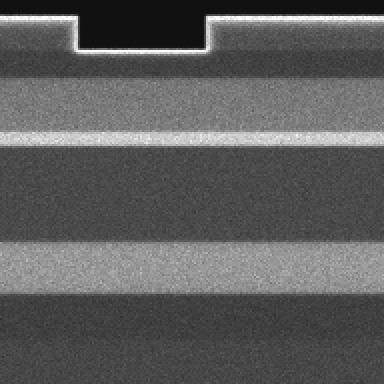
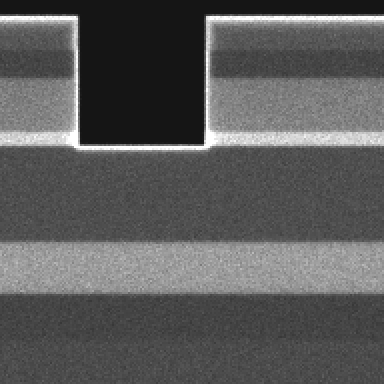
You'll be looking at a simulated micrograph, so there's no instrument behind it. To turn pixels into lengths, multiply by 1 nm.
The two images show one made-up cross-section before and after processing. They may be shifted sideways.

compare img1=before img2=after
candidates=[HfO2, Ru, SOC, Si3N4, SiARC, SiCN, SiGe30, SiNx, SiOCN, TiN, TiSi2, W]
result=removed:HfO2 and Ru and SiNx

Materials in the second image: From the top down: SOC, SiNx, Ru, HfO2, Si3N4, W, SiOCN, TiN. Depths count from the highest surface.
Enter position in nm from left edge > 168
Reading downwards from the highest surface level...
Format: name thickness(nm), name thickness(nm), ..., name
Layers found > empty 130, Si3N4 96, W 52, SiOCN 46, TiN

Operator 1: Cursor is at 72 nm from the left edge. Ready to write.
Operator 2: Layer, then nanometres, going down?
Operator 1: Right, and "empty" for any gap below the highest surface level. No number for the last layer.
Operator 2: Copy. SOC 34, SiNx 28, Ru 54, HfO2 14, Si3N4 96, W 52, SiOCN 46, TiN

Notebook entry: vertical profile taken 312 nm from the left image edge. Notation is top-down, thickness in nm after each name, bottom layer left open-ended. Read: SOC 34, SiNx 28, Ru 54, HfO2 14, Si3N4 96, W 52, SiOCN 46, TiN